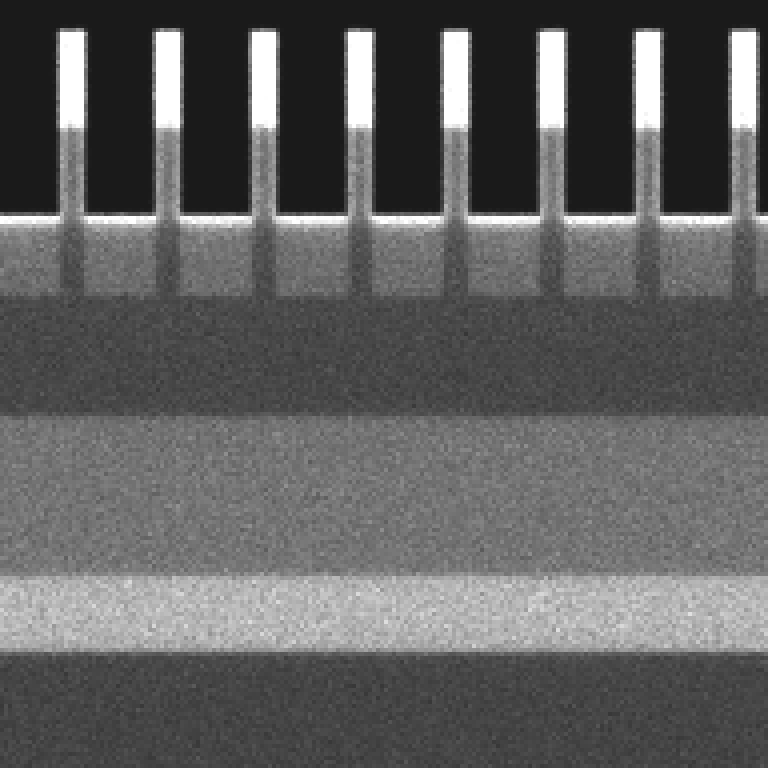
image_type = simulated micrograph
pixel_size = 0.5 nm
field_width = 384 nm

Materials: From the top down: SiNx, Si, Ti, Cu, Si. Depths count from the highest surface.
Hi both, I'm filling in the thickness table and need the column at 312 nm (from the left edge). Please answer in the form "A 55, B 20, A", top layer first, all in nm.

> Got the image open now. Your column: empty 92, SiNx 40, Si 60, Ti 80, Cu 38, Si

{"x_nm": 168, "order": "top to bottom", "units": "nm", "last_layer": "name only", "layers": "empty 92, SiNx 40, Si 60, Ti 80, Cu 38, Si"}